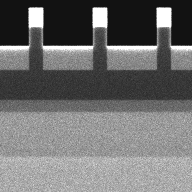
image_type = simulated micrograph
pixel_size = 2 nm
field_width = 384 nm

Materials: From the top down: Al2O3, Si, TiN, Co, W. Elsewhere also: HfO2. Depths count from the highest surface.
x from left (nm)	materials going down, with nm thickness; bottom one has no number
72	HfO2 38, Si 146, TiN 24, Co 90, W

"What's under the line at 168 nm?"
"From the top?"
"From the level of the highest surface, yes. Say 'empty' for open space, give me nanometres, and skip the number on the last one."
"empty 76, Al2O3 48, Si 60, TiN 24, Co 90, W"